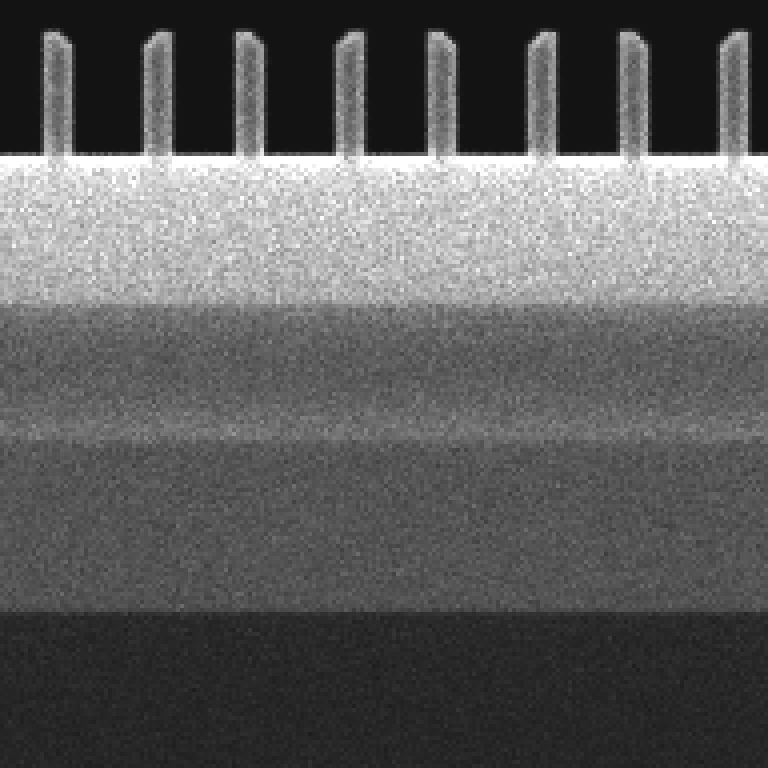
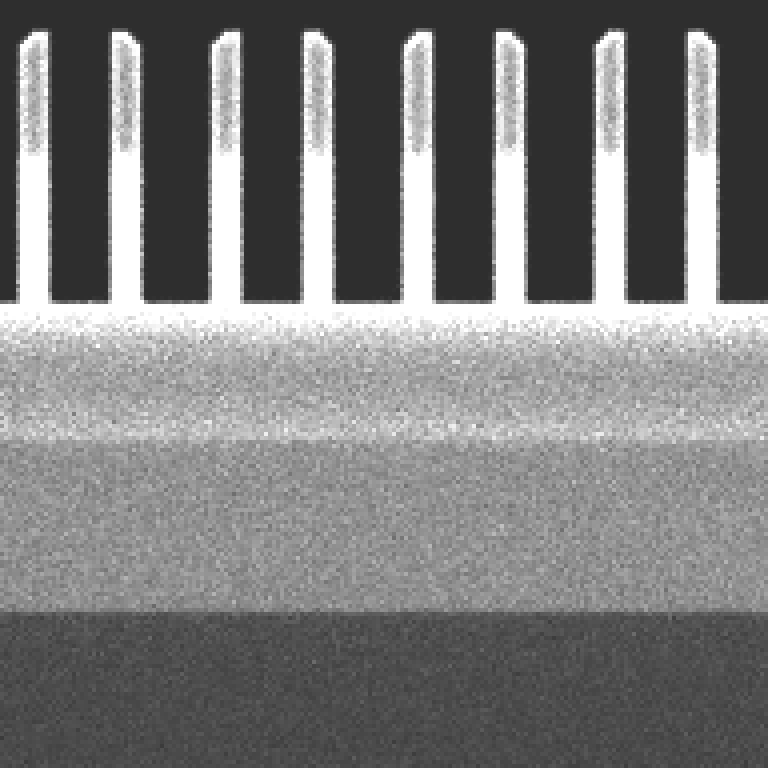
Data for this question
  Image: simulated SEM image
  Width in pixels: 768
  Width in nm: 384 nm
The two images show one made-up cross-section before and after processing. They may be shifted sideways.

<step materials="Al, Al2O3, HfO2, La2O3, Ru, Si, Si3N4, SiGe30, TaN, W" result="removed HfO2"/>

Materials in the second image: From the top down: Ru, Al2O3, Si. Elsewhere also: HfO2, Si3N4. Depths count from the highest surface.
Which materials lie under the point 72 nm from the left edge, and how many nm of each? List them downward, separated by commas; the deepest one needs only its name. empty 136, Ru 68, Al2O3 86, Si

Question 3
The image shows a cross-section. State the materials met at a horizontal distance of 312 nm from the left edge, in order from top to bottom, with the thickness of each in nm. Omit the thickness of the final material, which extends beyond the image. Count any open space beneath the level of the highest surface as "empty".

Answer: empty 136, Ru 68, Al2O3 86, Si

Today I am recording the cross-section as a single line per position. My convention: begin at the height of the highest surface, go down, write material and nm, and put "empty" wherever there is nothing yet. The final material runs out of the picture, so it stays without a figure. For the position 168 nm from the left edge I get empty 136, Ru 68, Al2O3 86, Si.